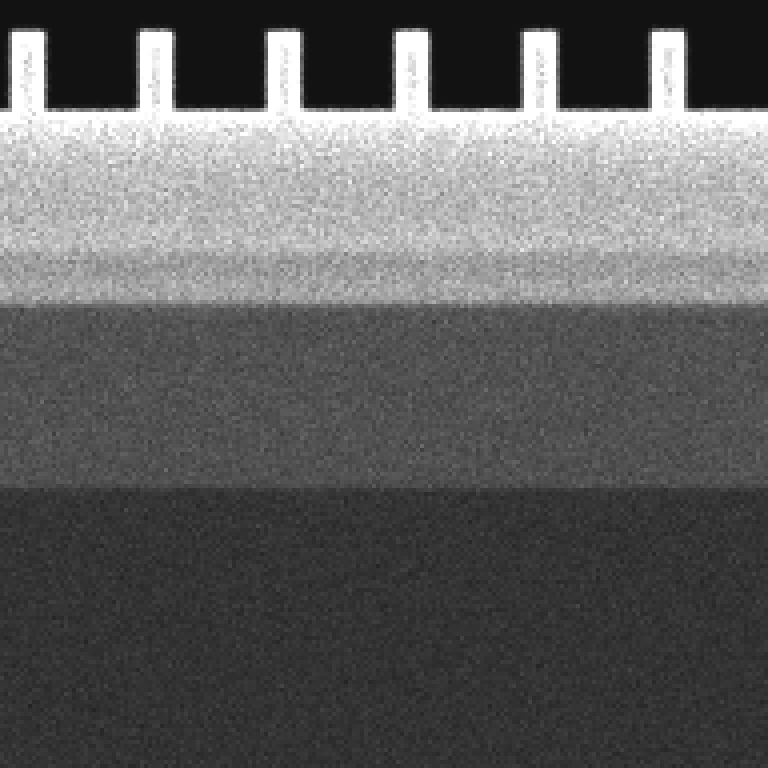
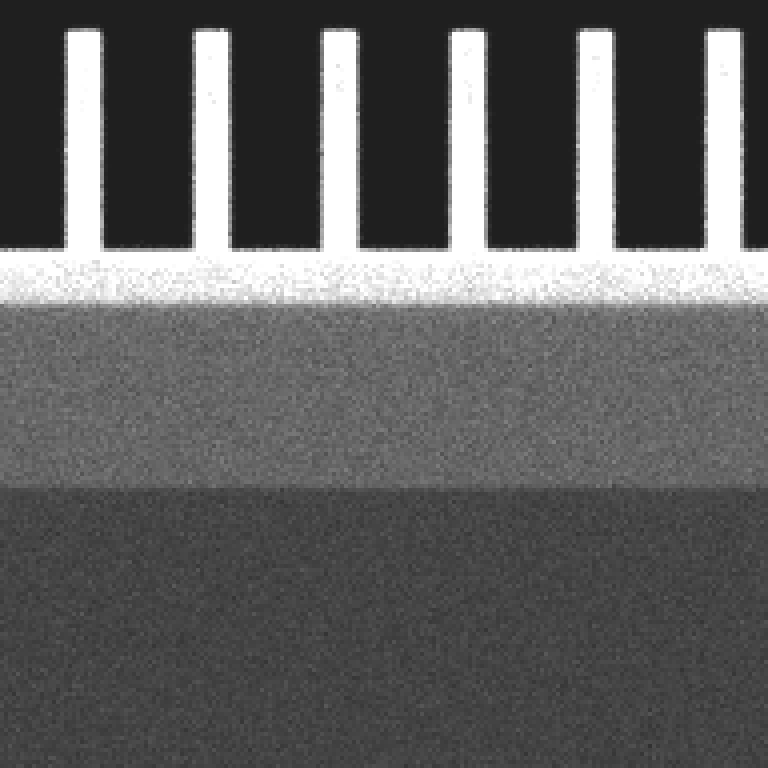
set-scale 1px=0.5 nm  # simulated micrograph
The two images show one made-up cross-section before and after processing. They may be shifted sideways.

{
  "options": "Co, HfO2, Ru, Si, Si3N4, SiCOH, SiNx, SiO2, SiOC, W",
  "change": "removed",
  "material": "W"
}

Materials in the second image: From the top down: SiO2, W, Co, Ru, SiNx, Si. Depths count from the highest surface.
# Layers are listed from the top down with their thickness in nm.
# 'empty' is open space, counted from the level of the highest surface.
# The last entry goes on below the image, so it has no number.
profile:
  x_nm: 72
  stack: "empty 110, Co 14, Ru 12, SiNx 92, Si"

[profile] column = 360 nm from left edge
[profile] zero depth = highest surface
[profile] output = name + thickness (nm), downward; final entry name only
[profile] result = SiO2 40, W 70, Co 14, Ru 12, SiNx 92, Si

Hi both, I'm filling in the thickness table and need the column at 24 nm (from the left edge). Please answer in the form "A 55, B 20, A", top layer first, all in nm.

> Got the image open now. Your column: empty 110, Co 14, Ru 12, SiNx 92, Si